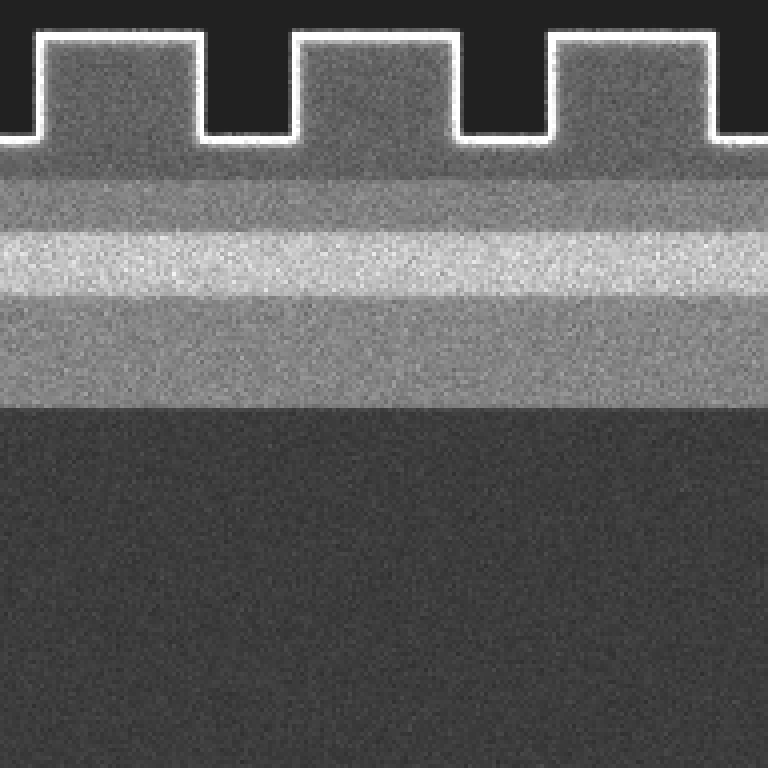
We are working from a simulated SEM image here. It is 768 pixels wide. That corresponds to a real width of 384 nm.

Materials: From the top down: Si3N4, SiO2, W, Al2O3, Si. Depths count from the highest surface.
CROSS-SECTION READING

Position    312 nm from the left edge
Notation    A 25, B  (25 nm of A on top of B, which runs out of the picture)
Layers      Si3N4 74, SiO2 26, W 32, Al2O3 56, Si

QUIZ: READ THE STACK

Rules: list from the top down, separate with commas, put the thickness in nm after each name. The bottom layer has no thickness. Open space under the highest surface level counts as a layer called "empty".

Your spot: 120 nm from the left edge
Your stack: empty 52, Si3N4 22, SiO2 26, W 32, Al2O3 56, Si